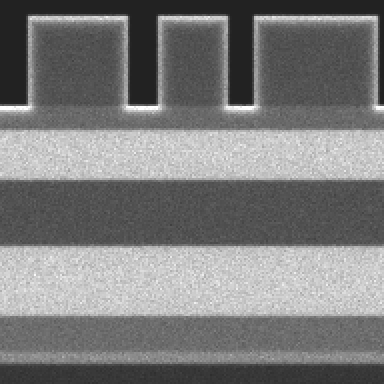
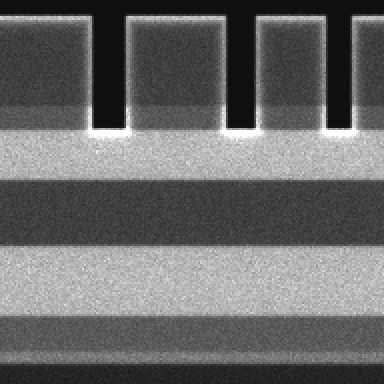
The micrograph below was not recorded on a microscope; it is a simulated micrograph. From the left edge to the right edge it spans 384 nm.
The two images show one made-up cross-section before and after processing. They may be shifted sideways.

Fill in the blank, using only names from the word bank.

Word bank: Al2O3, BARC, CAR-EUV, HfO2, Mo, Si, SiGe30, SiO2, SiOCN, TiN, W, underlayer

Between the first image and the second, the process removed SiO2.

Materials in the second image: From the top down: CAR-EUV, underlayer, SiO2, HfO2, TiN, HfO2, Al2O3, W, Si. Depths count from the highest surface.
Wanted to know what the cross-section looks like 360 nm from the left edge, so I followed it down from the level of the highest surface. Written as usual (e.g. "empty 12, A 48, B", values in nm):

CAR-EUV 64, underlayer 26, SiO2 24, HfO2 50, TiN 66, HfO2 70, Al2O3 36, W 12, Si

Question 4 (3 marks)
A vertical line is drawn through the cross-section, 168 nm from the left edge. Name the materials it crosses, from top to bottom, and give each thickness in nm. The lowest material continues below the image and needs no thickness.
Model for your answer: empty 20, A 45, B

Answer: CAR-EUV 64, underlayer 26, SiO2 24, HfO2 50, TiN 66, HfO2 70, Al2O3 36, W 12, Si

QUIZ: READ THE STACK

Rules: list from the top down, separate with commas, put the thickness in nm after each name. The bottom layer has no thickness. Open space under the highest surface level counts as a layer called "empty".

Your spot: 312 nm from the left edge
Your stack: CAR-EUV 64, underlayer 26, SiO2 24, HfO2 50, TiN 66, HfO2 70, Al2O3 36, W 12, Si